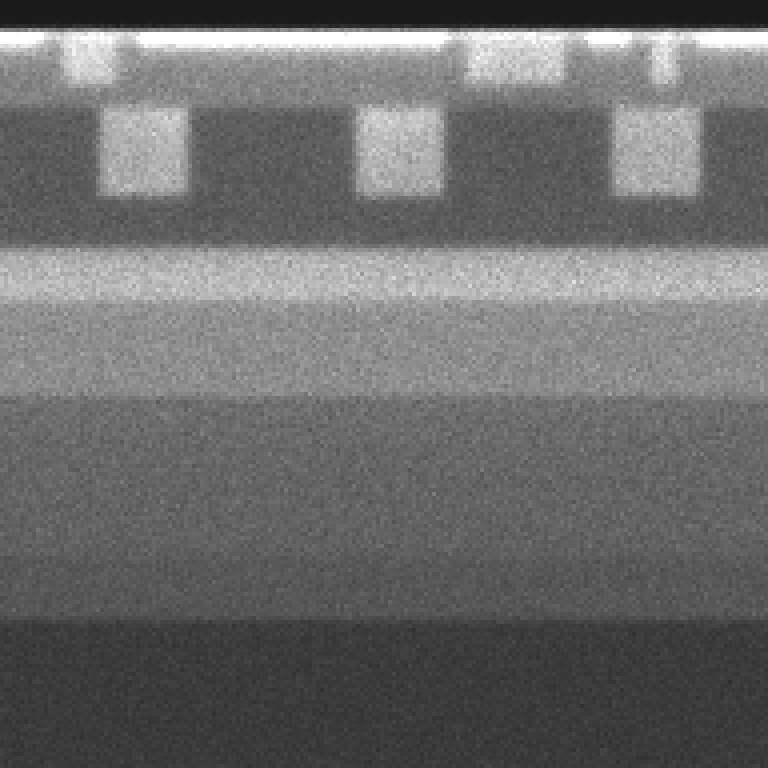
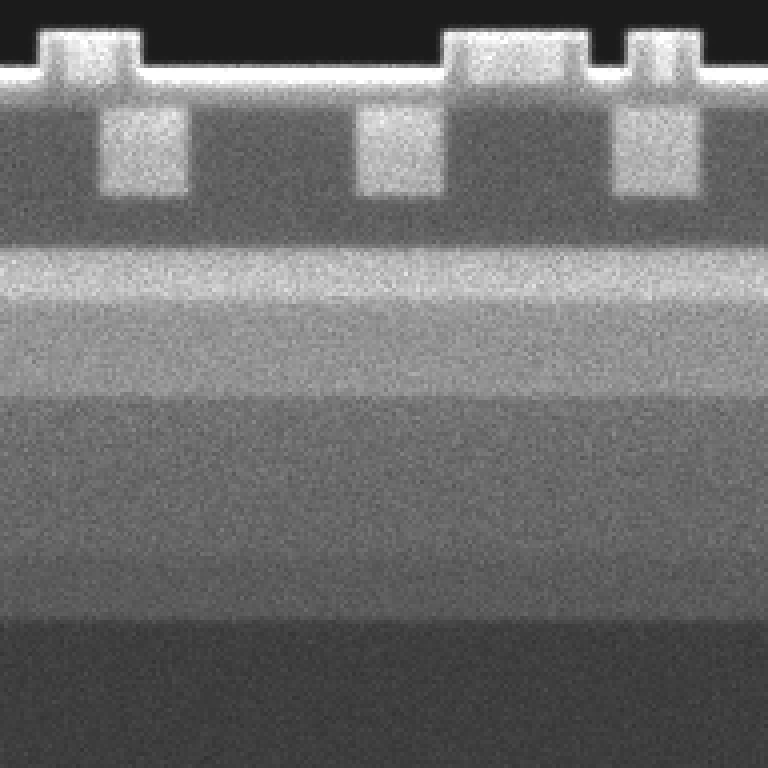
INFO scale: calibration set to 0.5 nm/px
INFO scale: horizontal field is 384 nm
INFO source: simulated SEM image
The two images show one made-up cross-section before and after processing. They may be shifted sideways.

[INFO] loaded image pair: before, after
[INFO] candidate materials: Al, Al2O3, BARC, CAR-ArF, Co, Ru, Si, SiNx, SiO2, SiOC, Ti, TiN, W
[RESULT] removed SiO2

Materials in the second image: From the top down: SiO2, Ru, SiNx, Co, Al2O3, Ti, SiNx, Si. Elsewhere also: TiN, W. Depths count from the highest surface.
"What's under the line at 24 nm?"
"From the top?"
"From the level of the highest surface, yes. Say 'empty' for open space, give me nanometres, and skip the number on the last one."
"TiN 38, SiNx 70, Co 26, Al2O3 48, Ti 80, SiNx 32, Si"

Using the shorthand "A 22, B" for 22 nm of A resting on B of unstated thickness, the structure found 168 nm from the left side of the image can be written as empty 18, SiO2 20, SiNx 70, Co 26, Al2O3 48, Ti 80, SiNx 32, Si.